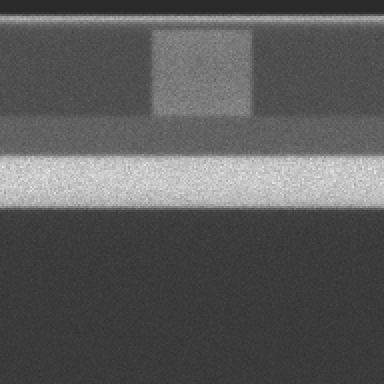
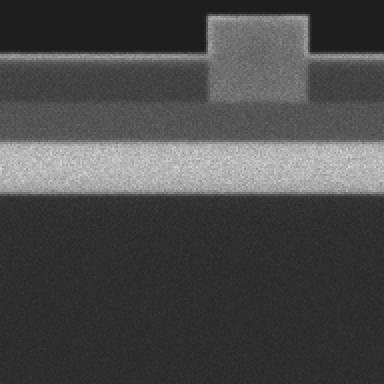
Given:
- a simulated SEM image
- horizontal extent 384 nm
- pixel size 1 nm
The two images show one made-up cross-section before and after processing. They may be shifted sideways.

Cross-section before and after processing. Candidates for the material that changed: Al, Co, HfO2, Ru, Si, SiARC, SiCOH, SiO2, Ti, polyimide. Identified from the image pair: SiARC (removed).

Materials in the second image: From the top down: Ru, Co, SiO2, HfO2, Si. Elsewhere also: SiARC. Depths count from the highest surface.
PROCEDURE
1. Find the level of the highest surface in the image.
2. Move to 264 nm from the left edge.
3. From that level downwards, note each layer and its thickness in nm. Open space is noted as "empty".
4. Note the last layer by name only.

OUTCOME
Ru 62, Co 24, SiO2 40, HfO2 52, Si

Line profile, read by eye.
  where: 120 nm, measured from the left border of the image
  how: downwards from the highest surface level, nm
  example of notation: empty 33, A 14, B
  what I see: empty 38, SiARC 48, SiO2 40, HfO2 52, Si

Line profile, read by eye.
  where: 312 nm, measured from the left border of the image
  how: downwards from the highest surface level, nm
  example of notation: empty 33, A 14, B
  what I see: empty 38, SiARC 48, SiO2 40, HfO2 52, Si